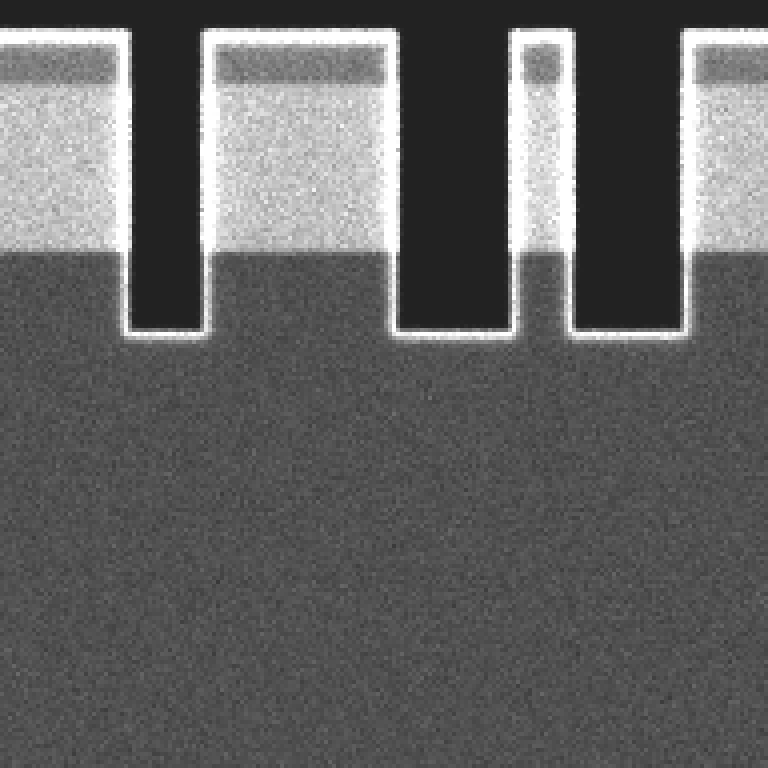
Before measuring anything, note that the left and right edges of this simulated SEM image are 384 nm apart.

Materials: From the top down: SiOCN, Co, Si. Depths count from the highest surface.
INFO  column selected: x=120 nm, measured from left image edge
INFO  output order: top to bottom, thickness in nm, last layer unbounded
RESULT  SiOCN 26, Co 84, Si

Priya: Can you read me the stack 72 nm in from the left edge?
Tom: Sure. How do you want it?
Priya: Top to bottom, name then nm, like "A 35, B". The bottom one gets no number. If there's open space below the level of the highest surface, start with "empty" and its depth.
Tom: empty 150, Si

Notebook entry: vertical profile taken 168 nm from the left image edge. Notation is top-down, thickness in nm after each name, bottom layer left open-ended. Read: SiOCN 26, Co 84, Si